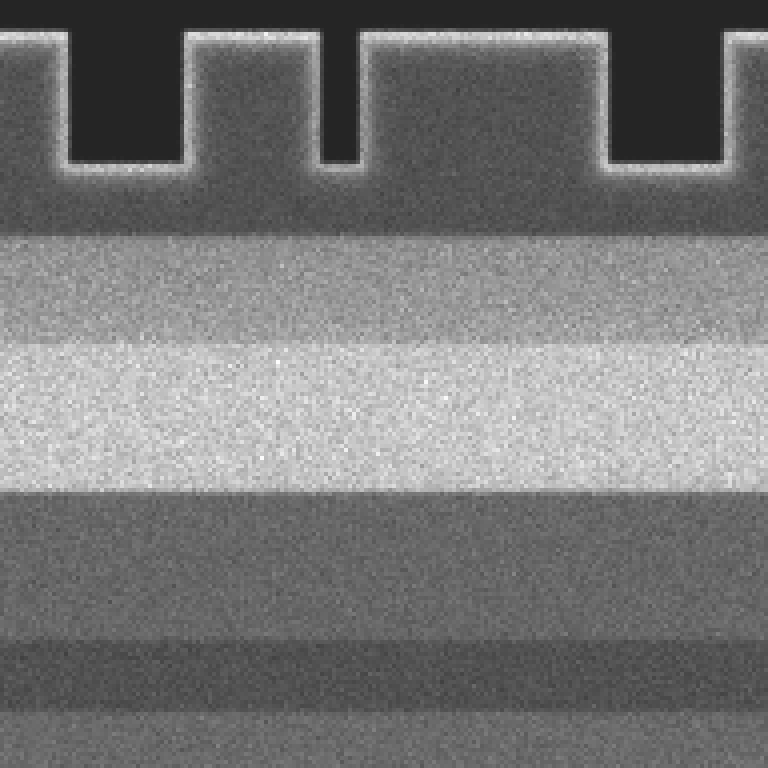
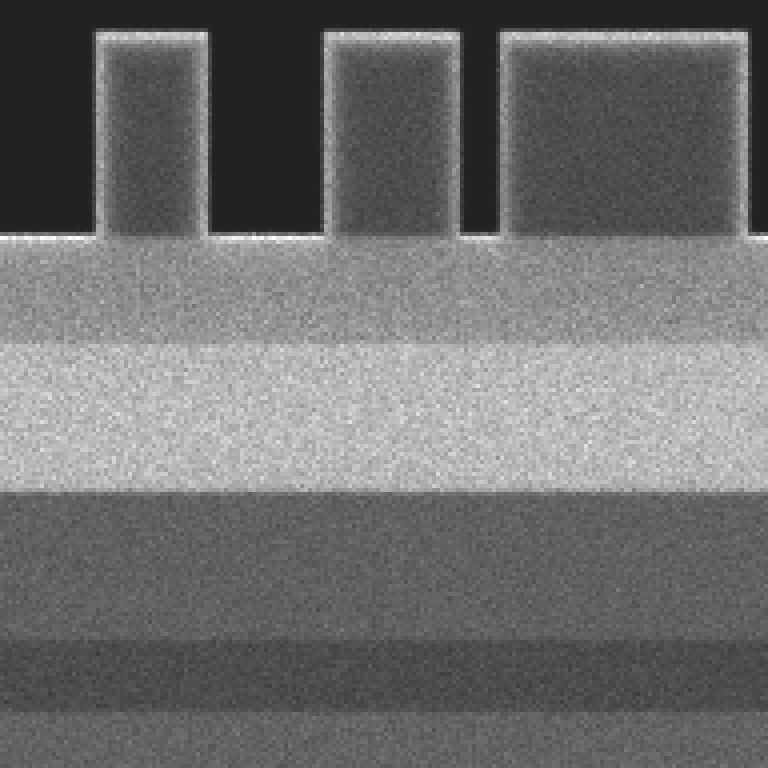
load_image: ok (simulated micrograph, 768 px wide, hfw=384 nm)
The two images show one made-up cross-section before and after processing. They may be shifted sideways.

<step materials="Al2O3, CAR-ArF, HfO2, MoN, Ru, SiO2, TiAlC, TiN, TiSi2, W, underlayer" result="removed underlayer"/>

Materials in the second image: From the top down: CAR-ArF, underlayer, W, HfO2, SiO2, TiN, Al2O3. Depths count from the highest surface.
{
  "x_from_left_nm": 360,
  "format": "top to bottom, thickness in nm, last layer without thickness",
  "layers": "CAR-ArF 66, underlayer 36, W 54, HfO2 74, SiO2 74, TiN 36, Al2O3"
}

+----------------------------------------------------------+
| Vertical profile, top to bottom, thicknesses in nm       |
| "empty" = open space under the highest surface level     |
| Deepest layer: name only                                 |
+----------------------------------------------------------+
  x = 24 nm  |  empty 102, W 54, HfO2 74, SiO2 74, TiN 36, Al2O3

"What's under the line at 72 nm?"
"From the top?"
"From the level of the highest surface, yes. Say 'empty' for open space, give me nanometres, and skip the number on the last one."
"CAR-ArF 66, underlayer 36, W 54, HfO2 74, SiO2 74, TiN 36, Al2O3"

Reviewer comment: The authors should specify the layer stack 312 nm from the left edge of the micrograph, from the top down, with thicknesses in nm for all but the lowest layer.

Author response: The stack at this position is CAR-ArF 66, underlayer 36, W 54, HfO2 74, SiO2 74, TiN 36, Al2O3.